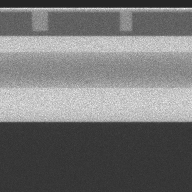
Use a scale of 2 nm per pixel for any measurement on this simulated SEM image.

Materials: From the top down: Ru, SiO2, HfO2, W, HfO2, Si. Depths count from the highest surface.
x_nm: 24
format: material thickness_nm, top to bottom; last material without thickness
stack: Ru 8, SiO2 48, HfO2 32, W 72, HfO2 68, Si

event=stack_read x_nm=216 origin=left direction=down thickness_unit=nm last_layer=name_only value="Ru 8, SiO2 48, HfO2 32, W 72, HfO2 68, Si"